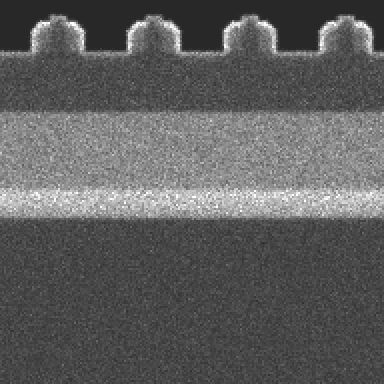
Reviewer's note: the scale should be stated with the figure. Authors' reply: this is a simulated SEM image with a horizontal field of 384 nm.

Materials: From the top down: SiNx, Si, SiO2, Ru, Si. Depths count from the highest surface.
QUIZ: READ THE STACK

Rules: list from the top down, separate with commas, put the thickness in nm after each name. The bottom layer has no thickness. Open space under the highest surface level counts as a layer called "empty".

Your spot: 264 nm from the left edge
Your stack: empty 6, SiNx 30, Si 60, SiO2 78, Ru 28, Si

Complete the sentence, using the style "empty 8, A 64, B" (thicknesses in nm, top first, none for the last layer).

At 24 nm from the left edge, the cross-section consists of empty 36, Si 60, SiO2 78, Ru 28, Si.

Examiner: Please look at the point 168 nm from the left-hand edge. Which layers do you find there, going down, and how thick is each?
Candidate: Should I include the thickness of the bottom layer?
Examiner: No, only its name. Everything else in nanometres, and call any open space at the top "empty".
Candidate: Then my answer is empty 6, SiNx 30, Si 60, SiO2 78, Ru 28, Si